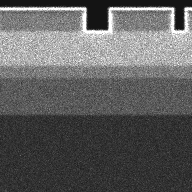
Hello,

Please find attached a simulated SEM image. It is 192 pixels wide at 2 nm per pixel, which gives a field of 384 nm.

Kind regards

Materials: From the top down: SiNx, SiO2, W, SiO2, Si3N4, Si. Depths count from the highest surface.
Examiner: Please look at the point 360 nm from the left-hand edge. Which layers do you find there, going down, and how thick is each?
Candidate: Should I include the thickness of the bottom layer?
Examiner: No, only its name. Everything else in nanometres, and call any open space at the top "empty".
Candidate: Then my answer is empty 46, W 70, SiO2 24, Si3N4 74, Si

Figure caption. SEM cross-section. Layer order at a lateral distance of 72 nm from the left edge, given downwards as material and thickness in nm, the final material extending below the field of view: SiNx 10, SiO2 36, W 70, SiO2 24, Si3N4 74, Si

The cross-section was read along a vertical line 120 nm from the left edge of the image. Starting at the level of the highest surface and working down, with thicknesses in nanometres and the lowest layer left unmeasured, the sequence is SiNx 10, SiO2 36, W 70, SiO2 24, Si3N4 74, Si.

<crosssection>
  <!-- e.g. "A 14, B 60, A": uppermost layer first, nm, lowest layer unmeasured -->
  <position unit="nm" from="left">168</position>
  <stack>SiNx 10, SiO2 36, W 70, SiO2 24, Si3N4 74, Si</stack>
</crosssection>